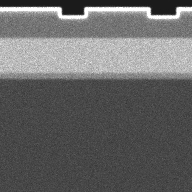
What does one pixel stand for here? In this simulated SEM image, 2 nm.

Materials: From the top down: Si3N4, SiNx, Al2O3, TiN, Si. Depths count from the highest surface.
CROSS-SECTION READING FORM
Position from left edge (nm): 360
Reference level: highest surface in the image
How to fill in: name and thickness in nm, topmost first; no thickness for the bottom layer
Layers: Si3N4 16, SiNx 44, Al2O3 70, TiN 12, Si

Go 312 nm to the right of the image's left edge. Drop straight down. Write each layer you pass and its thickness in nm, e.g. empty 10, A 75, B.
empty 16, SiNx 44, Al2O3 70, TiN 12, Si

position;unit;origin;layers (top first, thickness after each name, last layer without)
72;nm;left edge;Si3N4 16, SiNx 44, Al2O3 70, TiN 12, Si